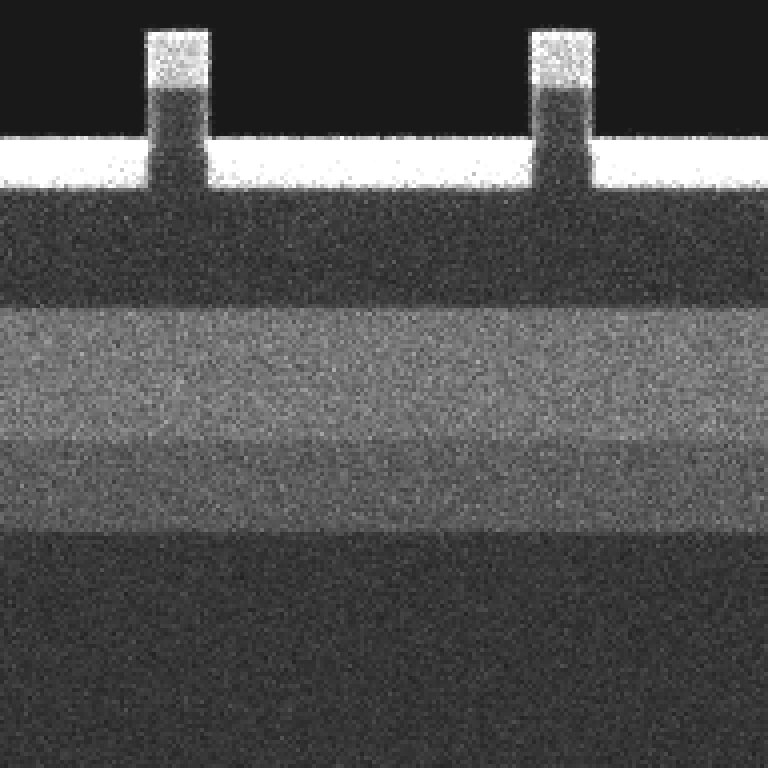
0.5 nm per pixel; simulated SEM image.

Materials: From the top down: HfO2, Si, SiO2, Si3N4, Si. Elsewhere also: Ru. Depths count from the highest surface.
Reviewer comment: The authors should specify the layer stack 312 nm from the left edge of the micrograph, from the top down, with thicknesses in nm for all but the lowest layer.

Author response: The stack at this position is empty 54, HfO2 24, Si 60, SiO2 66, Si3N4 46, Si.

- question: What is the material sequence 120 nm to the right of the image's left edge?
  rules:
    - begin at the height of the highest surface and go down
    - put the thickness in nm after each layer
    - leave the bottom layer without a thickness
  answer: empty 54, HfO2 24, Si 60, SiO2 66, Si3N4 46, Si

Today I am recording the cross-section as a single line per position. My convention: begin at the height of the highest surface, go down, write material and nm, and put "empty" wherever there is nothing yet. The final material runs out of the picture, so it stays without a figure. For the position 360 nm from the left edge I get empty 54, HfO2 24, Si 60, SiO2 66, Si3N4 46, Si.